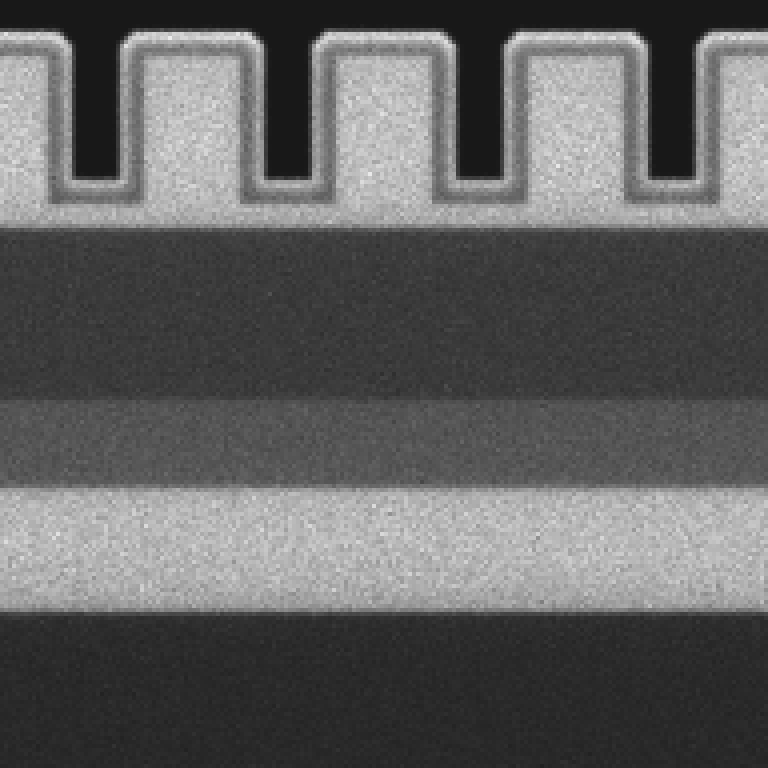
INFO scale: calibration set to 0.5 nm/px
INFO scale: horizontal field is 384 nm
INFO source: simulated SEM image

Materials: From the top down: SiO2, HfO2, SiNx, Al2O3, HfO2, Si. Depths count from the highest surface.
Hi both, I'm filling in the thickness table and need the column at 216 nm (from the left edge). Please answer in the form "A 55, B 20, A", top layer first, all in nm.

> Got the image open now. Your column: SiO2 86, HfO2 12, SiNx 86, Al2O3 44, HfO2 62, Si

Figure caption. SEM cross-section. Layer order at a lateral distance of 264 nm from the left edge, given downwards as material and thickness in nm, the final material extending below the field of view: SiO2 12, HfO2 86, SiNx 86, Al2O3 44, HfO2 62, Si